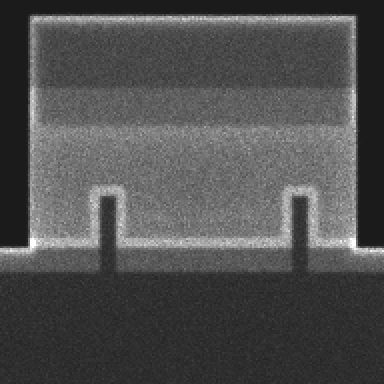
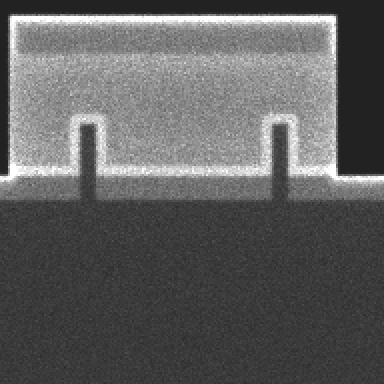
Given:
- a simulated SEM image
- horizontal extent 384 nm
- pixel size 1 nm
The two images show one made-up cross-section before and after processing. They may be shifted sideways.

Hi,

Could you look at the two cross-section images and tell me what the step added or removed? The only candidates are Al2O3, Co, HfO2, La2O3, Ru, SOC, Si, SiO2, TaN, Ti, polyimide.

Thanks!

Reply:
removed SOC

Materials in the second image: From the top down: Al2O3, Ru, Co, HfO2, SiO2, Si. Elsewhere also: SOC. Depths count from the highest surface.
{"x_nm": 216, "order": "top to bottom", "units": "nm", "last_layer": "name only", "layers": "Al2O3 38, Ru 96, Co 16, HfO2 10, SiO2 24, Si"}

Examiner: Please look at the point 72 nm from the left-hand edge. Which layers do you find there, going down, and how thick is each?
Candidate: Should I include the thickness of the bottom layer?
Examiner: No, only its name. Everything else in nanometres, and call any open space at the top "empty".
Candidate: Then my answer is Al2O3 38, Ru 44, Co 18, HfO2 60, SiO2 24, Si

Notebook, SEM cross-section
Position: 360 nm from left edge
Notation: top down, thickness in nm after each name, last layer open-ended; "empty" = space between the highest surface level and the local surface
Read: empty 160, SiO2 24, Si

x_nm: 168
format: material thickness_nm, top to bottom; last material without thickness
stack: Al2O3 38, Ru 96, Co 16, HfO2 10, SiO2 24, Si